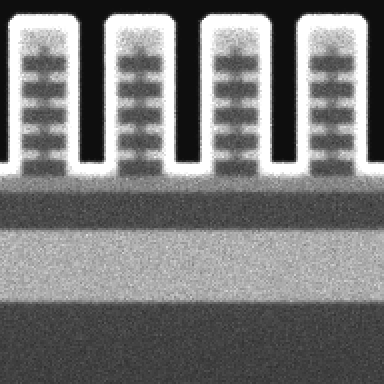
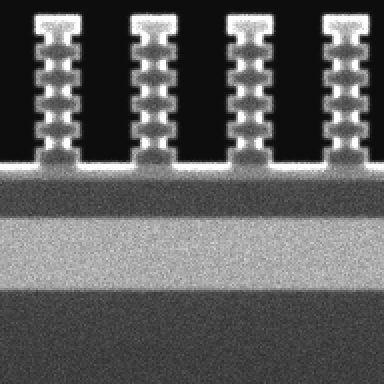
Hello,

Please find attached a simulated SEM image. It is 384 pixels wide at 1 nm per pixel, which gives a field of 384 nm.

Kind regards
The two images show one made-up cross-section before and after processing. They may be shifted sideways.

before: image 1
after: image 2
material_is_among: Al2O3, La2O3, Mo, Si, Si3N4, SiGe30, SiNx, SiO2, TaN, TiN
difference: Al2O3, removed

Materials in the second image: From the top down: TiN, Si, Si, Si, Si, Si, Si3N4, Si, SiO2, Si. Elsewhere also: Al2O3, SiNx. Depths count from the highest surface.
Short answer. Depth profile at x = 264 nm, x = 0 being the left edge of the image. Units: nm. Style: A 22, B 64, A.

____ TiN 18, empty 10, Si 16, empty 10, Si 16, empty 10, Si 16, empty 10, Si 16, empty 10, Si 16, Si3N4 16, Si 38, SiO2 72, Si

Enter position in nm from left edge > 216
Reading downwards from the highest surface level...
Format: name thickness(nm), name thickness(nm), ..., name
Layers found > empty 148, Si3N4 16, Si 38, SiO2 72, Si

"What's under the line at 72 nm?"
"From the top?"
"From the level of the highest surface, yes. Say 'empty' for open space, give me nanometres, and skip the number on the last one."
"TiN 18, empty 10, Si 16, empty 10, Si 16, empty 10, Si 16, empty 10, Si 16, empty 10, Si 16, Si3N4 16, Si 38, SiO2 72, Si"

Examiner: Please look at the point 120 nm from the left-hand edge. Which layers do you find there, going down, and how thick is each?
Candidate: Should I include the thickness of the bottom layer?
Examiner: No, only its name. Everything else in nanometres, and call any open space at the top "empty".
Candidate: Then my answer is empty 148, Si3N4 16, Si 38, SiO2 72, Si